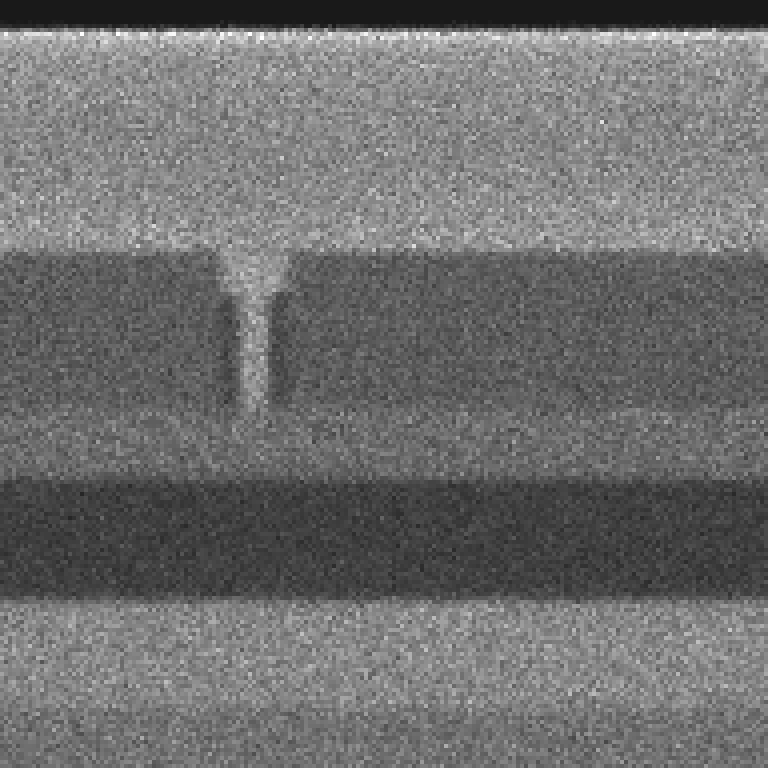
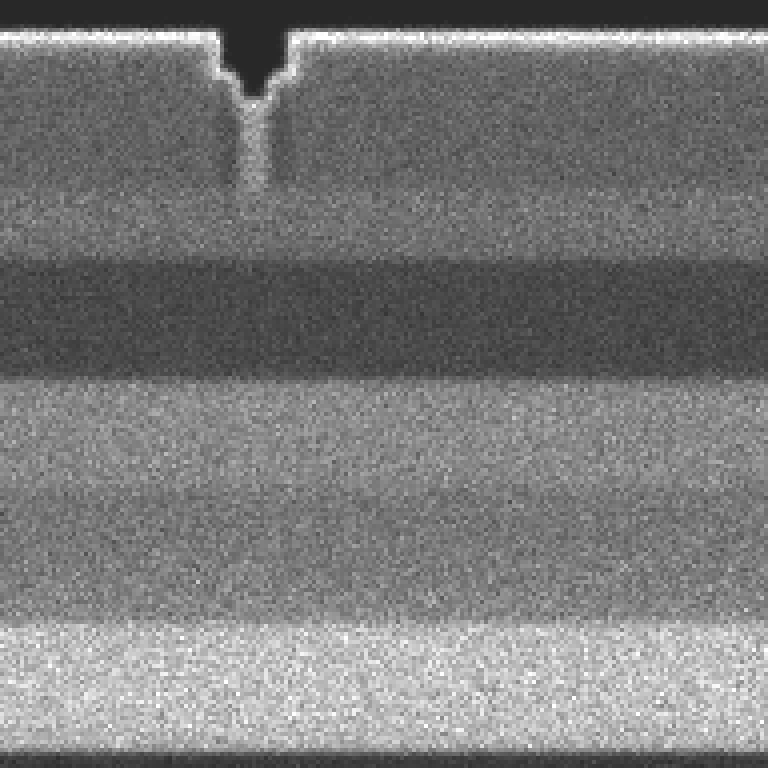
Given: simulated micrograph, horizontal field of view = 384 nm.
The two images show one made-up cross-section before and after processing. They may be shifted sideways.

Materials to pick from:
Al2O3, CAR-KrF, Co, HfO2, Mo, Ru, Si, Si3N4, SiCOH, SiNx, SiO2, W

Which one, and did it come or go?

W - removed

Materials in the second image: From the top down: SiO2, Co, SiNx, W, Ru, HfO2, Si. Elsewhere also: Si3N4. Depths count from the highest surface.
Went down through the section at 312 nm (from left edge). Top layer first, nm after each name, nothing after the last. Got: SiO2 78, Co 36, SiNx 60, W 54, Ru 68, HfO2 64, Si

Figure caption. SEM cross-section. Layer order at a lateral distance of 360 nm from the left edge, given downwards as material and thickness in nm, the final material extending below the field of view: SiO2 78, Co 36, SiNx 60, W 54, Ru 68, HfO2 64, Si